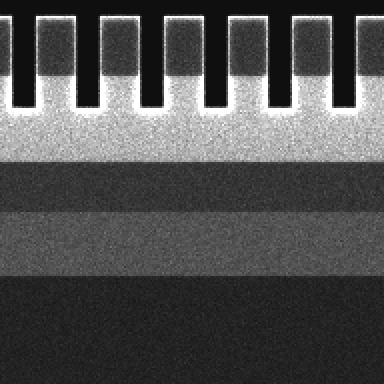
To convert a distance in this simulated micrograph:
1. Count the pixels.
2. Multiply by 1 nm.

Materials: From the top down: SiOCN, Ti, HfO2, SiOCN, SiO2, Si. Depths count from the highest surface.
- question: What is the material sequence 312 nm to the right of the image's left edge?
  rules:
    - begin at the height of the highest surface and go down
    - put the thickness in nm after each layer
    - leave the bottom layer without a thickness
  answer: SiOCN 10, Ti 50, HfO2 86, SiOCN 50, SiO2 64, Si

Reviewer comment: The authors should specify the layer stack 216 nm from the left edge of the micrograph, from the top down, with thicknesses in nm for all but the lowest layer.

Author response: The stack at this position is empty 92, HfO2 54, SiOCN 50, SiO2 64, Si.